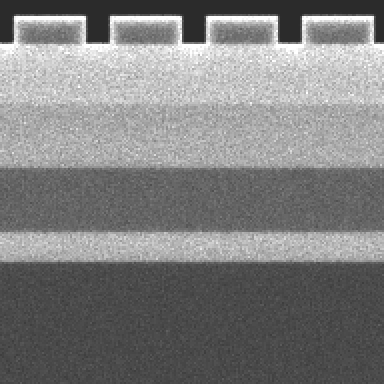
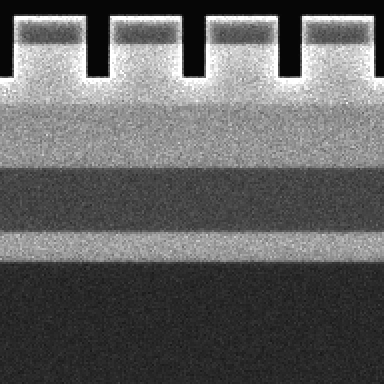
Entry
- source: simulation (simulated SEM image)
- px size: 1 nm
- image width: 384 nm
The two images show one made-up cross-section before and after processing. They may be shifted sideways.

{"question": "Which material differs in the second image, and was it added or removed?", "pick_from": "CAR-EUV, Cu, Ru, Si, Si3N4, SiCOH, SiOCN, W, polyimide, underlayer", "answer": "W, removed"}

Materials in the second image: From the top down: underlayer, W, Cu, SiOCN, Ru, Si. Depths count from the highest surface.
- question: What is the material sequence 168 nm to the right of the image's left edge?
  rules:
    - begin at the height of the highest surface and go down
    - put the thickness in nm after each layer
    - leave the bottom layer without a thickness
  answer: underlayer 28, W 60, Cu 64, SiOCN 64, Ru 30, Si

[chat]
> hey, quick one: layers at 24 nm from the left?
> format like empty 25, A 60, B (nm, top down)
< underlayer 28, W 60, Cu 64, SiOCN 64, Ru 30, Si